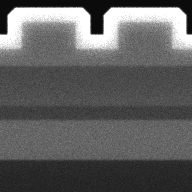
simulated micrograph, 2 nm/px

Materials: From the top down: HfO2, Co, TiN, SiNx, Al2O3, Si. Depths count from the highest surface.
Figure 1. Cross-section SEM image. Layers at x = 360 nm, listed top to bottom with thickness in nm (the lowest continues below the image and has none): empty 4, HfO2 78, Co 34, TiN 80, SiNx 28, Al2O3 80, Si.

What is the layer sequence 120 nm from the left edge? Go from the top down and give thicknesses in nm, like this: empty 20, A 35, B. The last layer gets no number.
HfO2 28, Co 88, TiN 80, SiNx 28, Al2O3 80, Si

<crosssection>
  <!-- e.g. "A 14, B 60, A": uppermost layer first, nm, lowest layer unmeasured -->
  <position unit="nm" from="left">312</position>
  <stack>HfO2 28, Co 88, TiN 80, SiNx 28, Al2O3 80, Si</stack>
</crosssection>